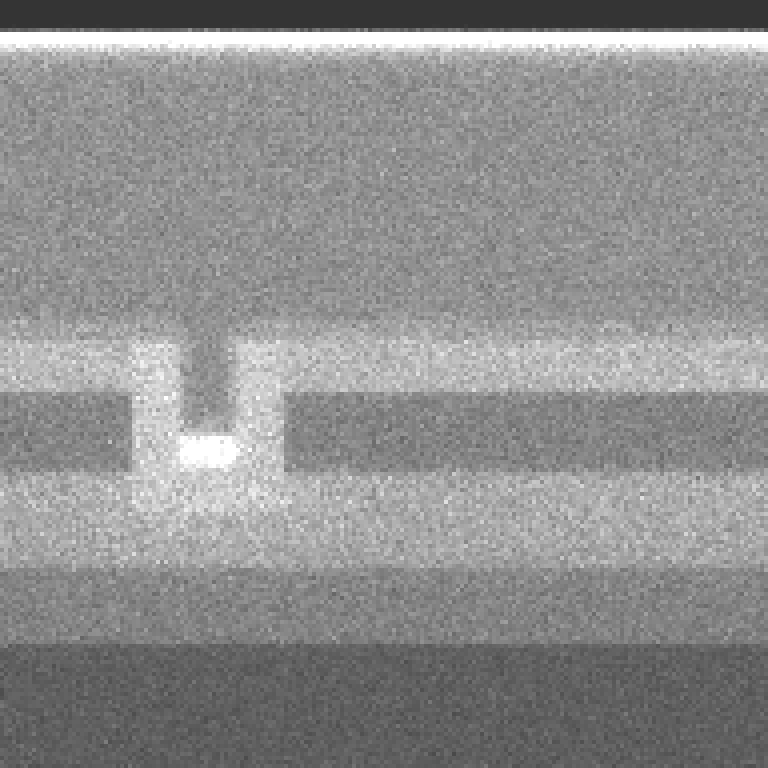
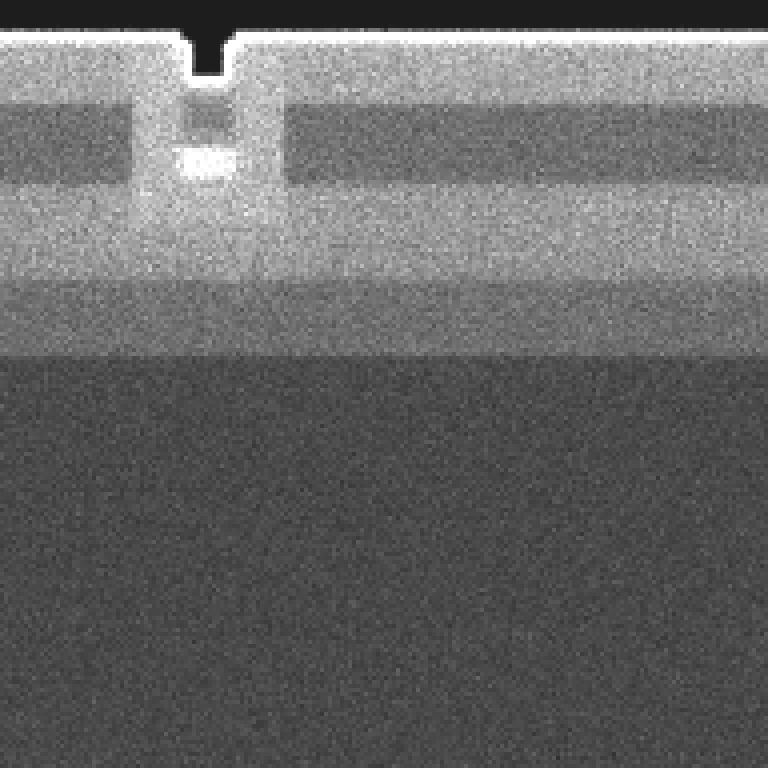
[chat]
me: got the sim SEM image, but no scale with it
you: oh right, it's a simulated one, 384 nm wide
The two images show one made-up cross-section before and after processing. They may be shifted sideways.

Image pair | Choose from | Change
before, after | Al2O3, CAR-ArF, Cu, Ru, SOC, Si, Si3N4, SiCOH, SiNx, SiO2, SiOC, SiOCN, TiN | SOC (removed)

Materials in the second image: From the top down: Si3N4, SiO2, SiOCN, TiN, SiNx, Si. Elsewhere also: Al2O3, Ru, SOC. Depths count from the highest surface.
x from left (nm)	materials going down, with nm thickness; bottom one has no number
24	Si3N4 10, SiO2 26, SiOCN 40, TiN 48, SiNx 38, Si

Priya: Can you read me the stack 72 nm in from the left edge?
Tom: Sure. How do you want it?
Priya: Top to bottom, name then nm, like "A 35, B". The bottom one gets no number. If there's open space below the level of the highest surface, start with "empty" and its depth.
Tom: Si3N4 10, Al2O3 86, TiN 28, SiNx 38, Si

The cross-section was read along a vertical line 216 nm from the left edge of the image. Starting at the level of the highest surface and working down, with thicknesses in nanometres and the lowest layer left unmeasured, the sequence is Si3N4 10, SiO2 26, SiOCN 40, TiN 48, SiNx 38, Si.